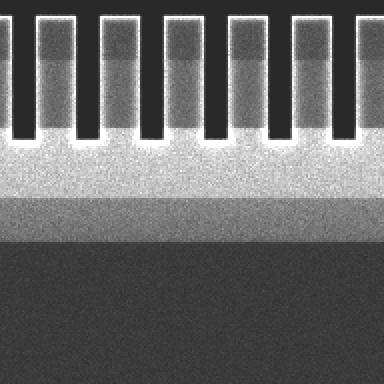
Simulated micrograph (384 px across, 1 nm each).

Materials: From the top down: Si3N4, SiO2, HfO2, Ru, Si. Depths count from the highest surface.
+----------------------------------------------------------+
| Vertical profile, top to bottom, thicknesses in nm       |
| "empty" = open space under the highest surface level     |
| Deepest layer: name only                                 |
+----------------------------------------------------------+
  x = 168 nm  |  Si3N4 44, SiO2 68, HfO2 70, Ru 44, Si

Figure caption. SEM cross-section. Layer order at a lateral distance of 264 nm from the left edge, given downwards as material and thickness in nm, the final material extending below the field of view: Si3N4 44, SiO2 68, HfO2 70, Ru 44, Si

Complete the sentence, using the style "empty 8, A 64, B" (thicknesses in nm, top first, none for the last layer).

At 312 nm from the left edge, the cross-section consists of Si3N4 44, SiO2 68, HfO2 70, Ru 44, Si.